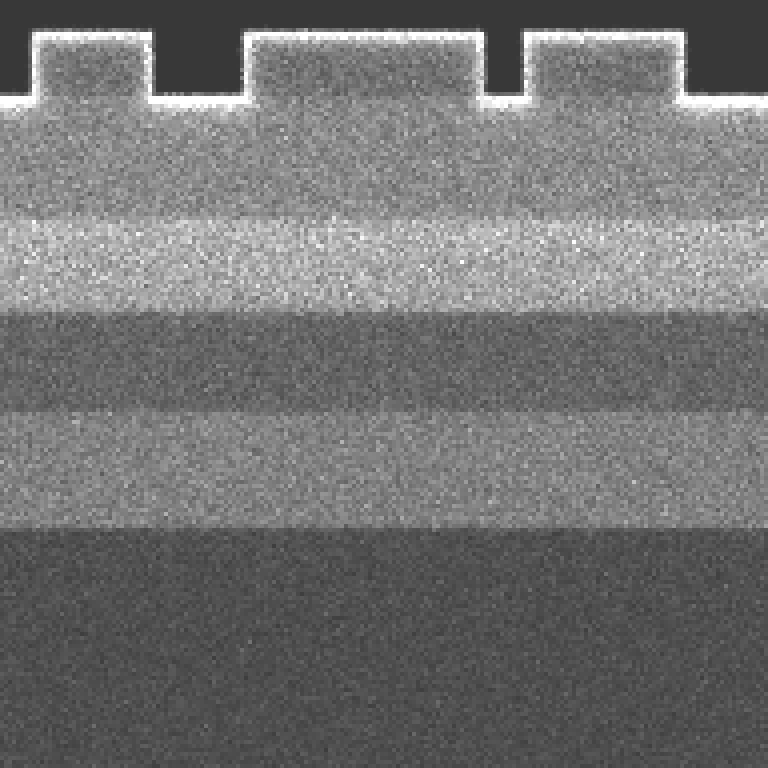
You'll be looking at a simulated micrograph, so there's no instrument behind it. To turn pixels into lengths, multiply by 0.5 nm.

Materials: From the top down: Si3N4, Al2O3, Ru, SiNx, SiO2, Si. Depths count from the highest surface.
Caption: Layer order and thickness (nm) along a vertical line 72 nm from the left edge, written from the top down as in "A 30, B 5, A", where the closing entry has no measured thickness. Si3N4 32, Al2O3 62, Ru 46, SiNx 50, SiO2 58, Si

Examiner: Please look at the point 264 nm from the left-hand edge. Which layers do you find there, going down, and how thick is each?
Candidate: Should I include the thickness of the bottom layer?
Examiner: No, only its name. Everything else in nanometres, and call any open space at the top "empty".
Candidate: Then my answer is Si3N4 32, Al2O3 62, Ru 46, SiNx 50, SiO2 58, Si